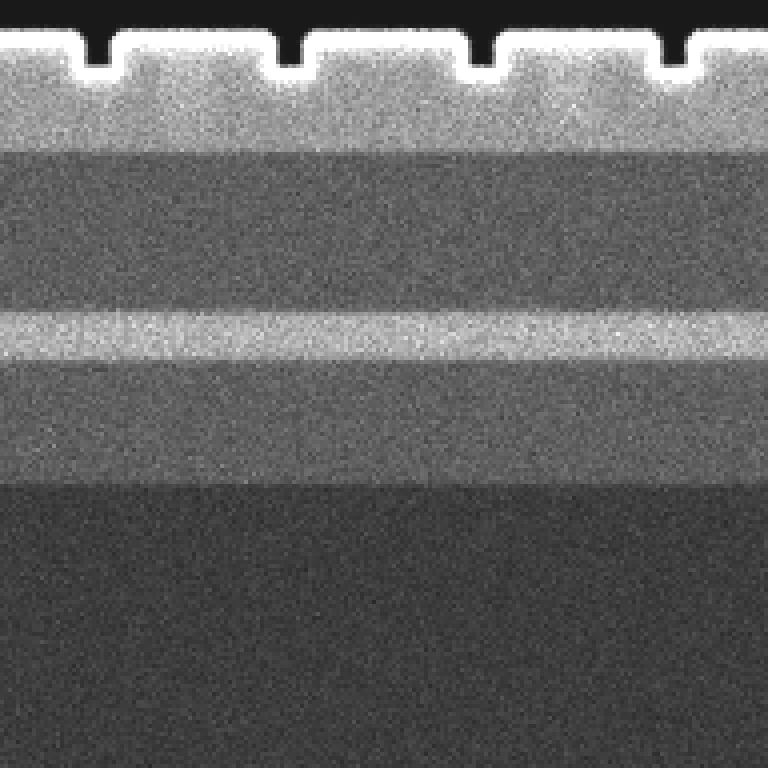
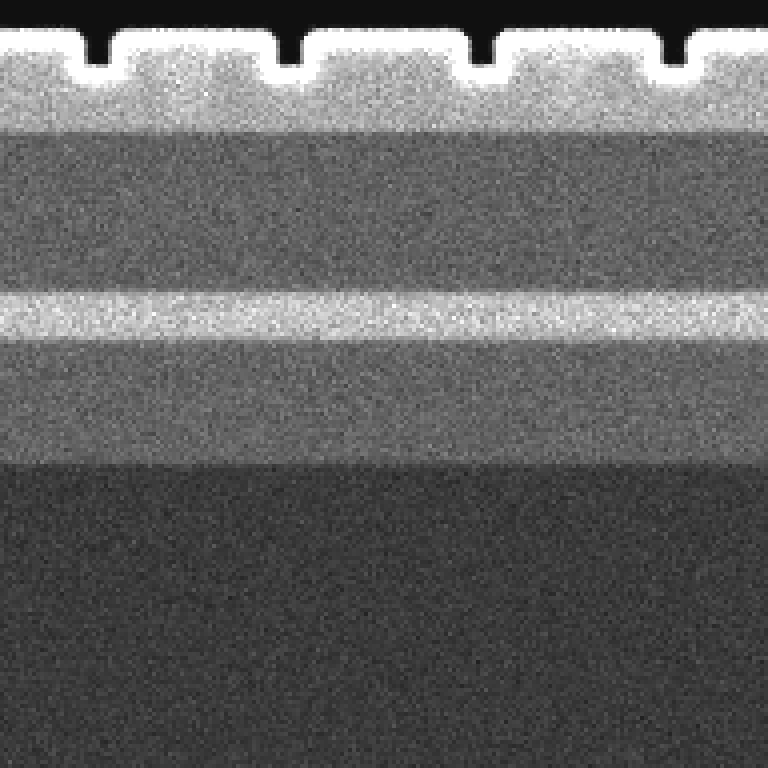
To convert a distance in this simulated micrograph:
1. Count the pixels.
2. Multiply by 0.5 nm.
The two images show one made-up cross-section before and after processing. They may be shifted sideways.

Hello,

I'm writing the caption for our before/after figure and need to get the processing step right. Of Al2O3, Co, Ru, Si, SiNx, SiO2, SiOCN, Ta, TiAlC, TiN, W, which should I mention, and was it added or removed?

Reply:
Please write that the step removed SiO2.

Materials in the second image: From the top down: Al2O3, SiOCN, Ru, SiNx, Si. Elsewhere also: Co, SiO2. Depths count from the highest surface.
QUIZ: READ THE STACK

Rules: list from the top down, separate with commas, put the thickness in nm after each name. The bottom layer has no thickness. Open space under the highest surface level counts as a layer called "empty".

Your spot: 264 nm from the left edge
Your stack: Al2O3 50, SiOCN 80, Ru 24, SiNx 62, Si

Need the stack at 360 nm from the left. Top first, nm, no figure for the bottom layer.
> Al2O3 50, SiOCN 80, Ru 24, SiNx 62, Si